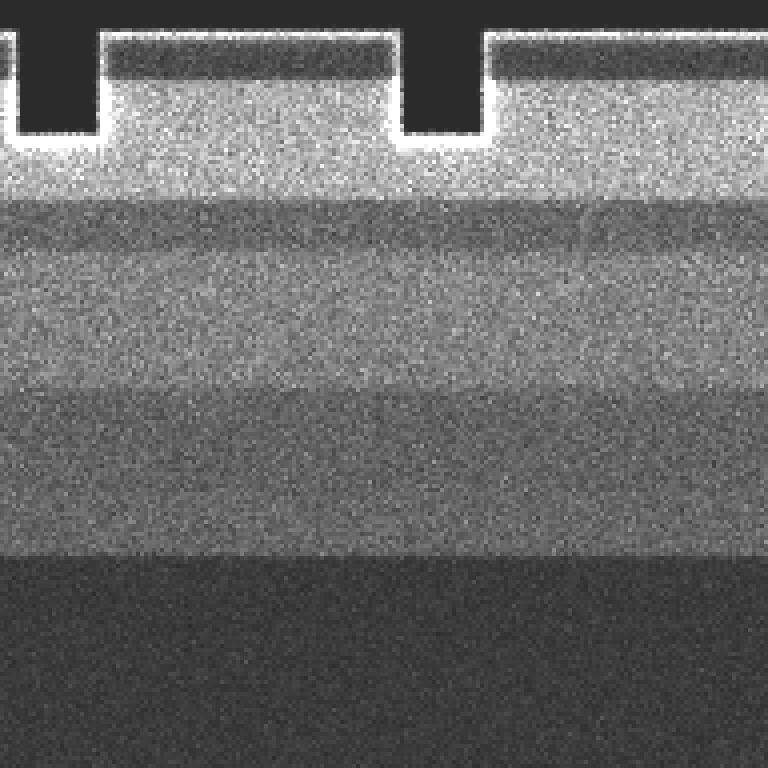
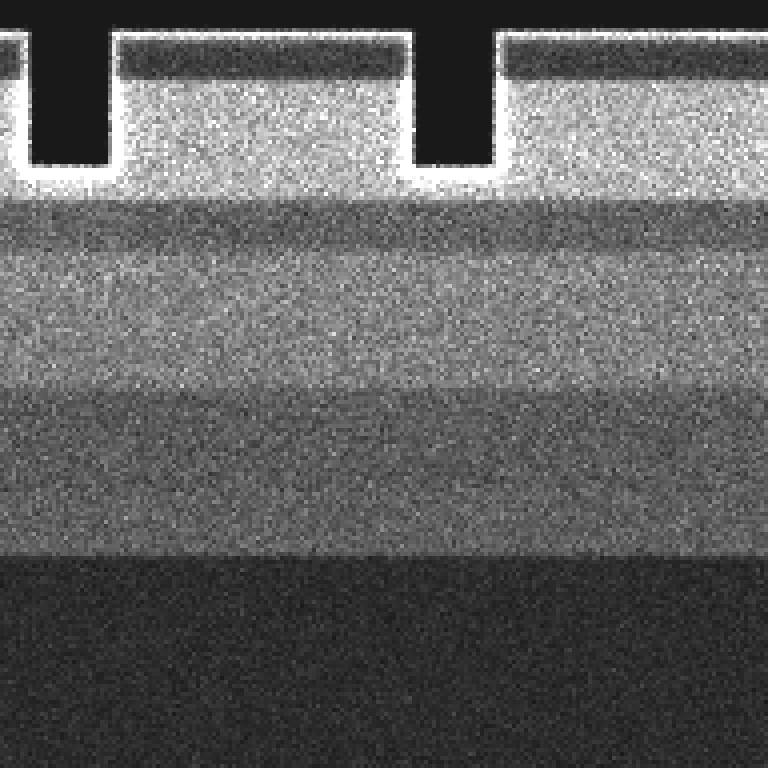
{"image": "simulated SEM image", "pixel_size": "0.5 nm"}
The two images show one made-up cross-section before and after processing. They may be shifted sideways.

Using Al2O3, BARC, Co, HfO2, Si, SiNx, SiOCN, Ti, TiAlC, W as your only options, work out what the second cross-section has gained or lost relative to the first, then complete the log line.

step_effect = removed HfO2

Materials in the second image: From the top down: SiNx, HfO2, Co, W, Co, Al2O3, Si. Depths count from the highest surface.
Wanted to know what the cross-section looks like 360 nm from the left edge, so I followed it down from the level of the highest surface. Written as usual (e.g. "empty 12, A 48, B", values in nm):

SiNx 24, HfO2 60, Co 26, W 68, Co 52, Al2O3 32, Si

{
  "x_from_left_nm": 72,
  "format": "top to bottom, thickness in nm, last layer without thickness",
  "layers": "SiNx 24, HfO2 60, Co 26, W 68, Co 52, Al2O3 32, Si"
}